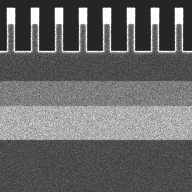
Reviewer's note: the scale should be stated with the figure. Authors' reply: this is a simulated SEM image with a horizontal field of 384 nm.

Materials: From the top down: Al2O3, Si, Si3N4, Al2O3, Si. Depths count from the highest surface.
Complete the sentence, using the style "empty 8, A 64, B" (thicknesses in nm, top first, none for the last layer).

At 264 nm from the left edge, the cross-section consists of Al2O3 32, Si 114, Si3N4 50, Al2O3 68, Si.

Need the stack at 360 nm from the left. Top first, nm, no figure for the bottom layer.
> Al2O3 32, Si 114, Si3N4 50, Al2O3 68, Si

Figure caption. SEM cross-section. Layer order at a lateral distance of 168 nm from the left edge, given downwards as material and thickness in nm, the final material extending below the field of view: Al2O3 32, Si 114, Si3N4 50, Al2O3 68, Si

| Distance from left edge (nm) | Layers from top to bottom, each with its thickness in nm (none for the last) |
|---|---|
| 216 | Al2O3 32, Si 114, Si3N4 50, Al2O3 68, Si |